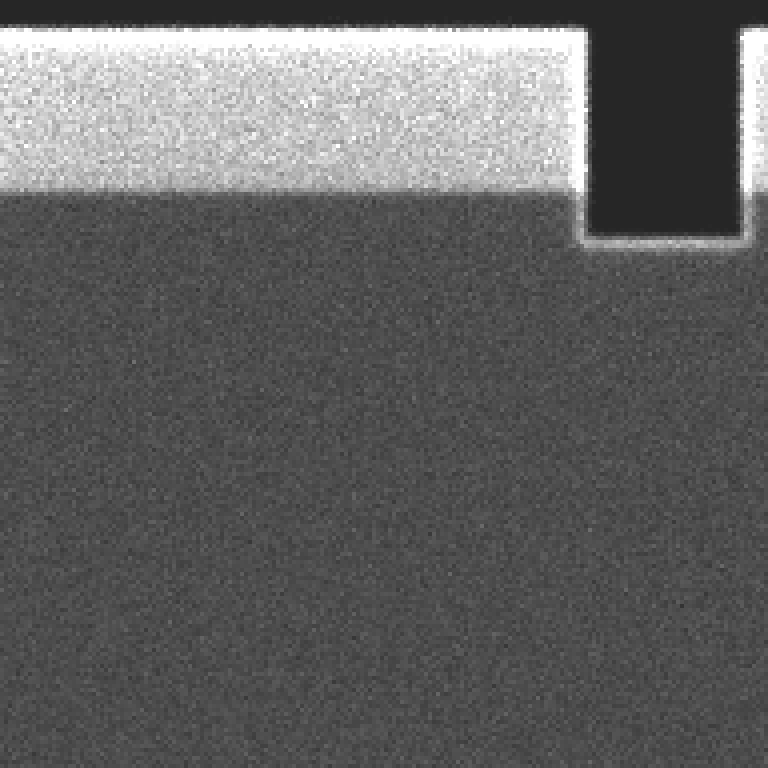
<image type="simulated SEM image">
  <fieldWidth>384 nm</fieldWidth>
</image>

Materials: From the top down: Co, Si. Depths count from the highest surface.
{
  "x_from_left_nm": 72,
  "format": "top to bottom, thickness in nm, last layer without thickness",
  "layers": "Co 80, Si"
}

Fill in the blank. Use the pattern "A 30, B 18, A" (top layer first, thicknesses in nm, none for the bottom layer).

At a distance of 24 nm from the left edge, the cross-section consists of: Co 80, Si